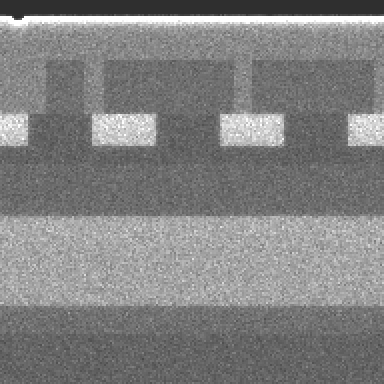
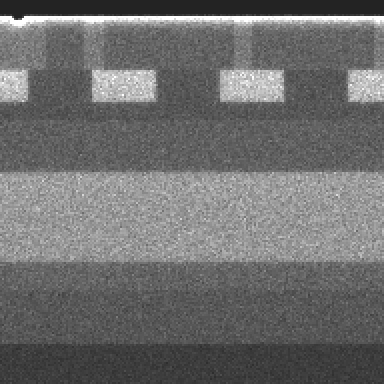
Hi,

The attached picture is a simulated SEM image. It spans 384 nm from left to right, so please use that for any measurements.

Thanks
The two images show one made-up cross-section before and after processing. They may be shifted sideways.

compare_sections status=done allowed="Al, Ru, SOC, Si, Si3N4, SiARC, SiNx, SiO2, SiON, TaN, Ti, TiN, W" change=removed material="SiO2"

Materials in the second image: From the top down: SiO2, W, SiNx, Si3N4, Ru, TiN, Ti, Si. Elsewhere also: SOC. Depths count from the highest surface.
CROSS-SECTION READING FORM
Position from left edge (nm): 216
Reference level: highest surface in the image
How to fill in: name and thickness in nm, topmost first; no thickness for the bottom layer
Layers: SOC 54, SiNx 50, Si3N4 52, Ru 90, TiN 28, Ti 54, Si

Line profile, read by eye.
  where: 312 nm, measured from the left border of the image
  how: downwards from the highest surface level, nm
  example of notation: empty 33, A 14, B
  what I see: SOC 54, SiNx 50, Si3N4 52, Ru 90, TiN 28, Ti 54, Si